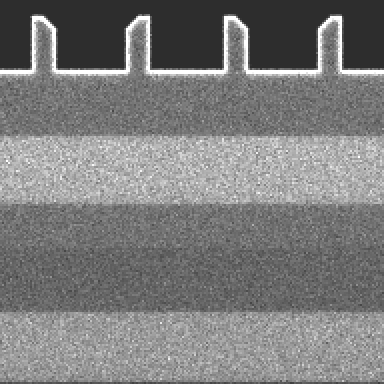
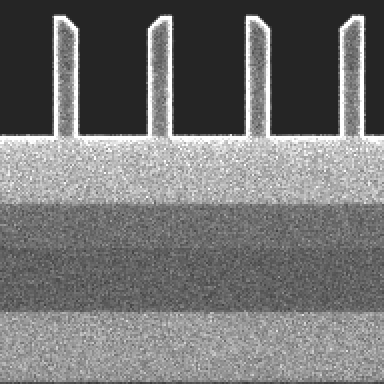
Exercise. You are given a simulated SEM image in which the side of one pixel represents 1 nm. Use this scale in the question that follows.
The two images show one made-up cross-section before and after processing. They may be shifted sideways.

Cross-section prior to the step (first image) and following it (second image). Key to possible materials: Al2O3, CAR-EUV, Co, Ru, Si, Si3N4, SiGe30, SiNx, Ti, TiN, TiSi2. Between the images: Si3N4 was removed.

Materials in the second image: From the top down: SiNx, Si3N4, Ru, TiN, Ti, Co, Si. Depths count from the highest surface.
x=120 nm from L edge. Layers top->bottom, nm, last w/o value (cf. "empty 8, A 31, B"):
empty 120, Ru 68, TiN 44, Ti 64, Co 70, Si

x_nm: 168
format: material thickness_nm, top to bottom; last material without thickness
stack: SiNx 54, Si3N4 66, Ru 68, TiN 44, Ti 64, Co 70, Si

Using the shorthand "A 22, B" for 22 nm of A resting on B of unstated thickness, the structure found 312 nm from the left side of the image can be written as empty 120, Ru 68, TiN 44, Ti 64, Co 70, Si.